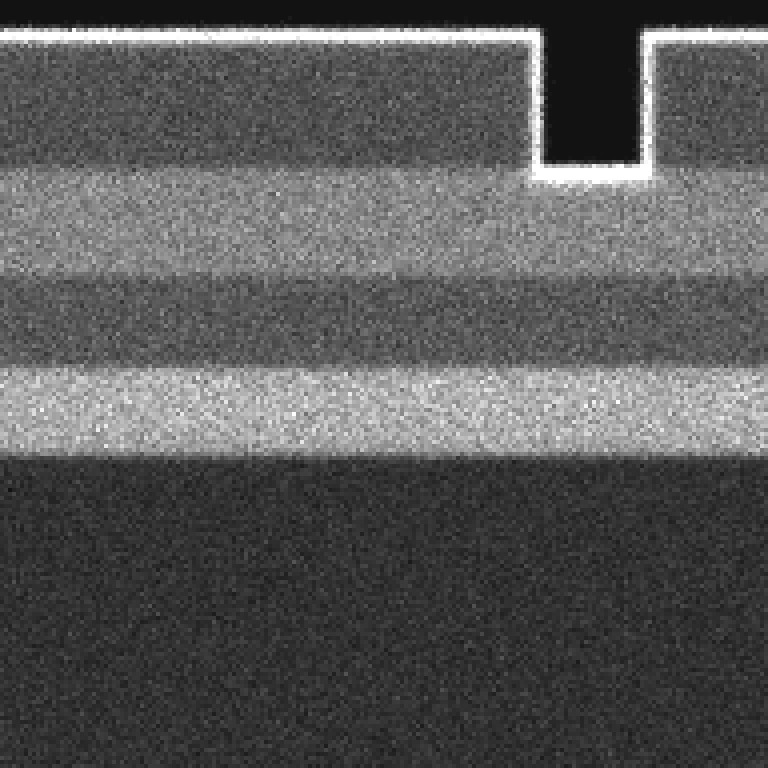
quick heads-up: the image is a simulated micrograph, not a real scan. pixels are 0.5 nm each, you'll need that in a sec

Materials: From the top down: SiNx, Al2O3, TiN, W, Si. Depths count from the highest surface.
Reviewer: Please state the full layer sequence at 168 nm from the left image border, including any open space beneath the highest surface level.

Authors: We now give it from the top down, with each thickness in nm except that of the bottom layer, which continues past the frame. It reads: SiNx 68, Al2O3 54, TiN 46, W 44, Si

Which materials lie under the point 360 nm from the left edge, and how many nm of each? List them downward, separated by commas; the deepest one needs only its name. SiNx 68, Al2O3 54, TiN 46, W 44, Si